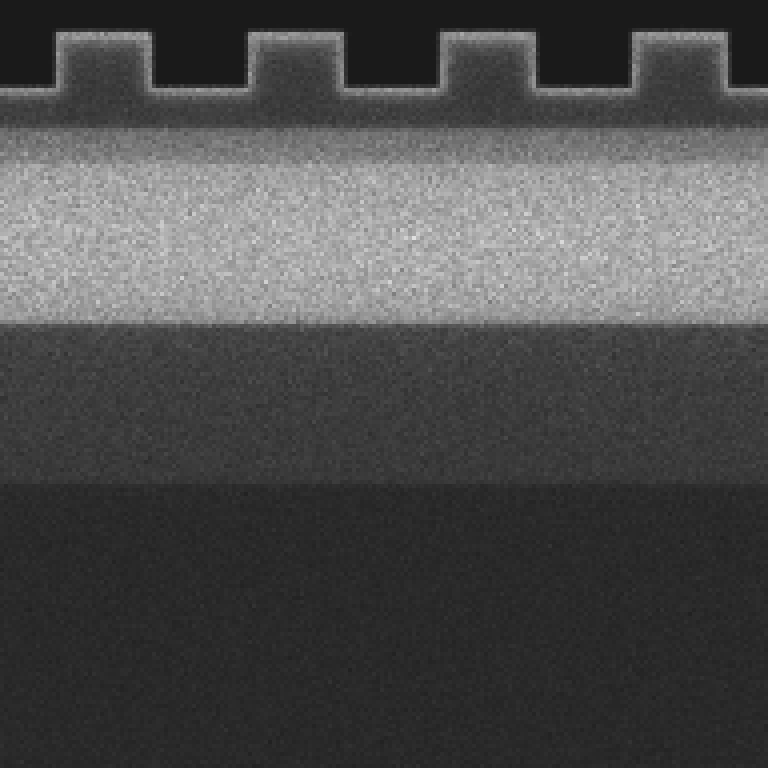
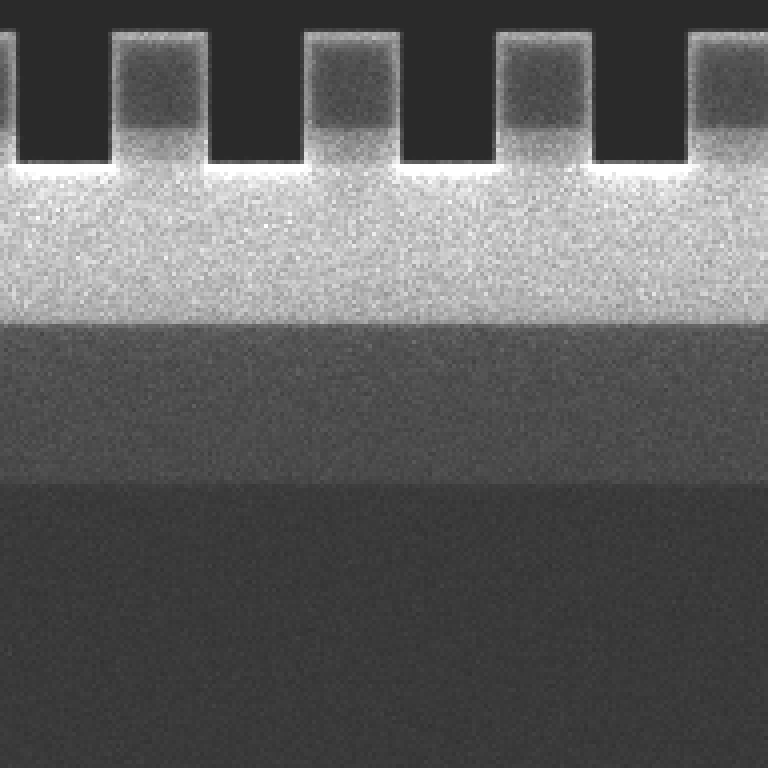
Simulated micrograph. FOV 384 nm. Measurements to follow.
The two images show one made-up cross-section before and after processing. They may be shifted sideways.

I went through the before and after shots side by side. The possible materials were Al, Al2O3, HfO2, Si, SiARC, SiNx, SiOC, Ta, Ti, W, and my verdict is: removed, SiNx and W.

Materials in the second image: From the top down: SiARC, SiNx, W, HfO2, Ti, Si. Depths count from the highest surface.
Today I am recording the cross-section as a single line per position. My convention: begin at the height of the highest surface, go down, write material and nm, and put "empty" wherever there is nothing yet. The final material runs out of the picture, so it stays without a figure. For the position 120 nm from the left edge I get empty 66, HfO2 80, Ti 80, Si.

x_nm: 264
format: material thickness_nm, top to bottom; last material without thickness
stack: SiARC 16, SiNx 32, W 18, HfO2 80, Ti 80, Si